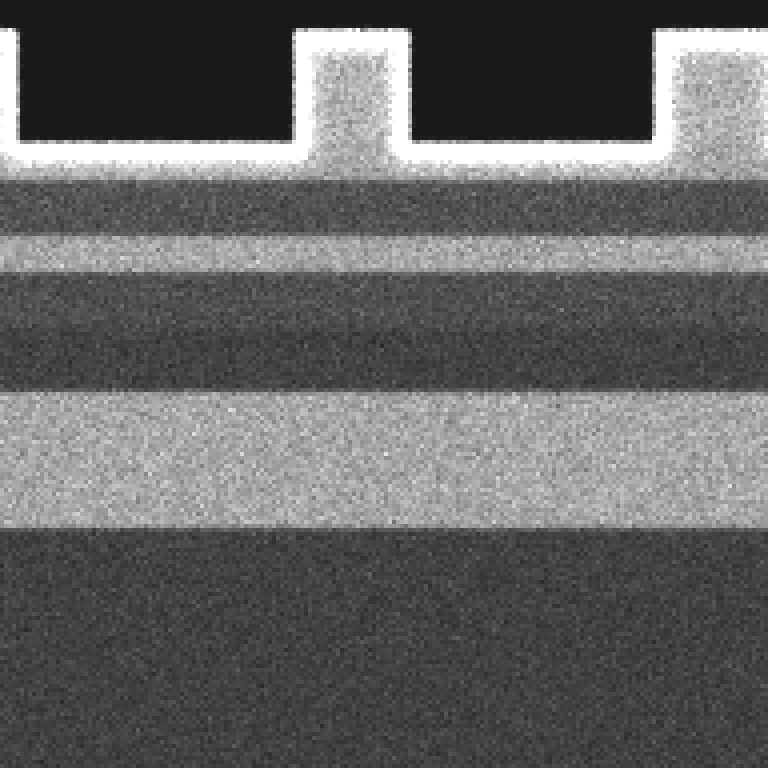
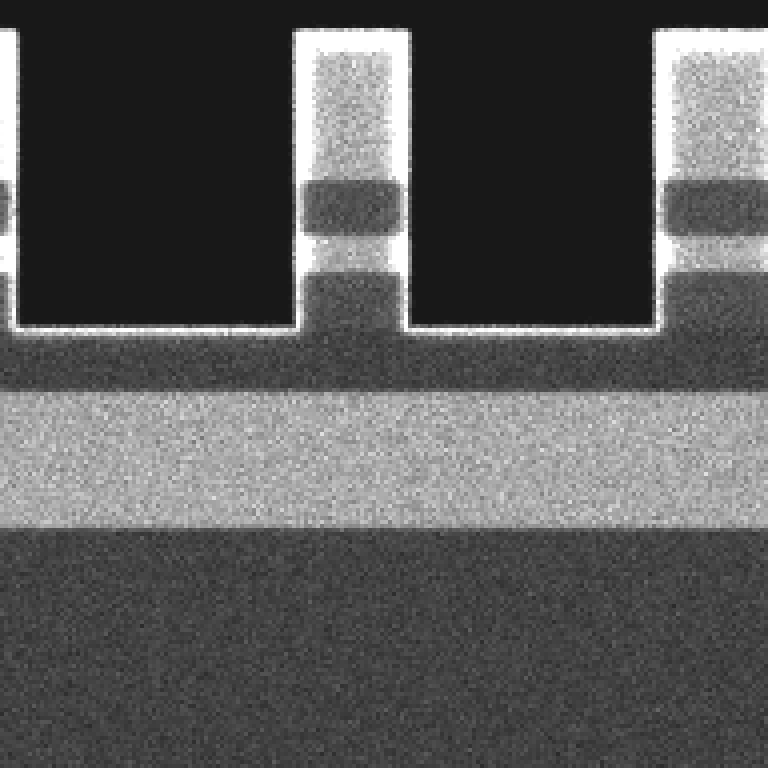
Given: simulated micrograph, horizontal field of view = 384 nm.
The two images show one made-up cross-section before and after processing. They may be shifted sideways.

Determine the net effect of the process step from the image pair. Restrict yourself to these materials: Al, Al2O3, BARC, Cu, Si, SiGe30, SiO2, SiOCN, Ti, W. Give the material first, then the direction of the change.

SiGe30 and SiO2: removed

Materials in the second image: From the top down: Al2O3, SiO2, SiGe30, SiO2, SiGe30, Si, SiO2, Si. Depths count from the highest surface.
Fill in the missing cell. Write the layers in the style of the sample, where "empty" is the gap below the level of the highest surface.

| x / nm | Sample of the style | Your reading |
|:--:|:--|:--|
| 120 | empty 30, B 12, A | empty 148, Si 32, SiO2 68, Si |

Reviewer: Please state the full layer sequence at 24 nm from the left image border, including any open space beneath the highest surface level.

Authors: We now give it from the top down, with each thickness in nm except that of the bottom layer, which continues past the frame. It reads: empty 148, Si 32, SiO2 68, Si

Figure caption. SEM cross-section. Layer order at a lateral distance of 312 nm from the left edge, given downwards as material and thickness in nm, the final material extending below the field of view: empty 148, Si 32, SiO2 68, Si